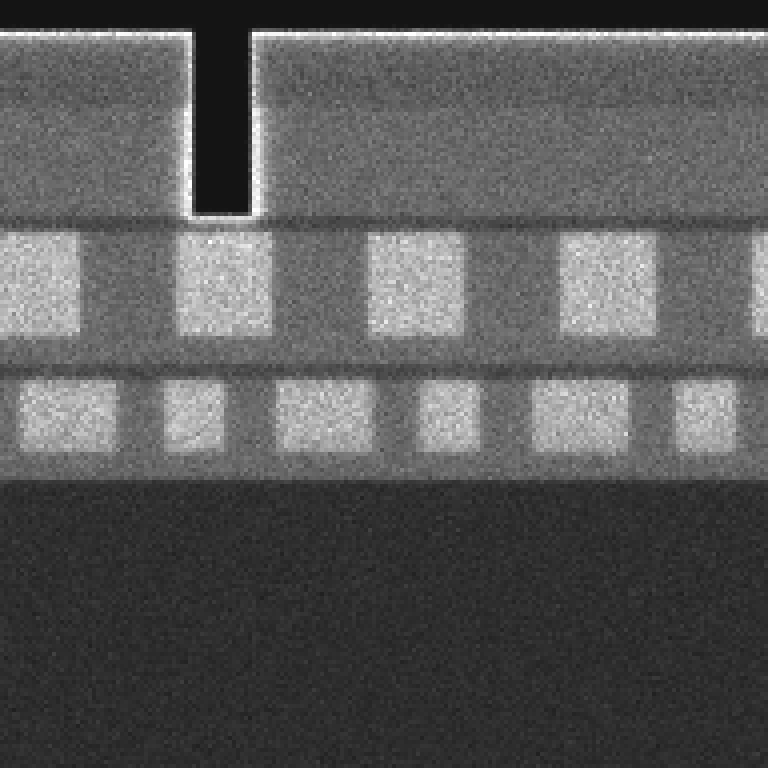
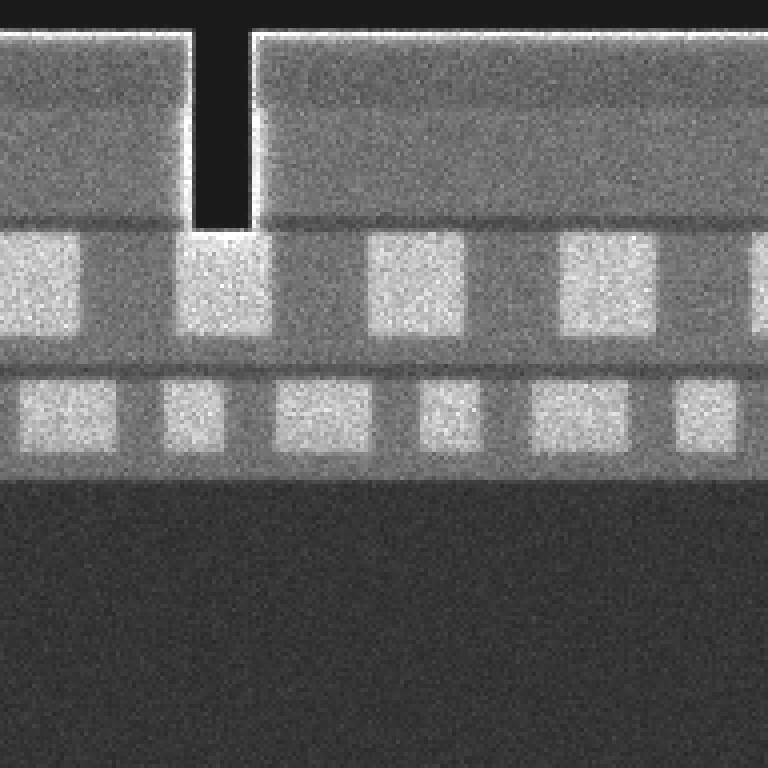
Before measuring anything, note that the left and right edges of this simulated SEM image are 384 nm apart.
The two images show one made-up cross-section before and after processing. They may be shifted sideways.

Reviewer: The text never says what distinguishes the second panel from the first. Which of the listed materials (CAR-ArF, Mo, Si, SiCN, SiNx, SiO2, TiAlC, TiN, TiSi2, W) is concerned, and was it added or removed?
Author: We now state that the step removed SiNx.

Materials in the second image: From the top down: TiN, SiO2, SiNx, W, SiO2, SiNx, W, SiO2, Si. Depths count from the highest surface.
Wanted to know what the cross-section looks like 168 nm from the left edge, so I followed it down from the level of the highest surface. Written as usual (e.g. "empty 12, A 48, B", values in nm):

TiN 38, SiO2 54, SiNx 8, SiO2 66, SiNx 8, W 36, SiO2 14, Si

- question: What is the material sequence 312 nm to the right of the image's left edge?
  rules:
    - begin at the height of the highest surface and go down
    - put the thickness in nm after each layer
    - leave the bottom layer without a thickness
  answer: TiN 38, SiO2 54, SiNx 8, W 52, SiO2 14, SiNx 8, W 36, SiO2 14, Si